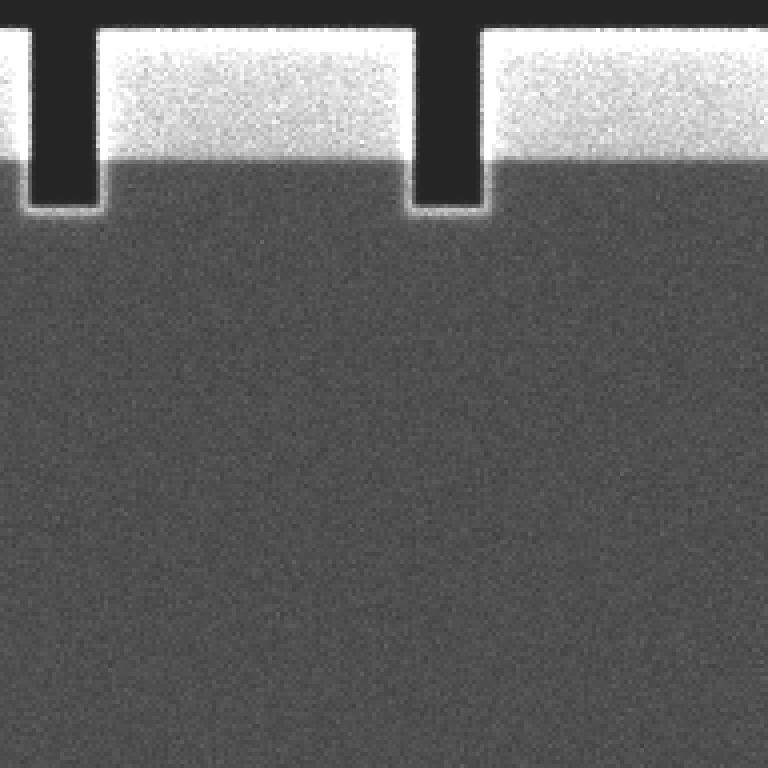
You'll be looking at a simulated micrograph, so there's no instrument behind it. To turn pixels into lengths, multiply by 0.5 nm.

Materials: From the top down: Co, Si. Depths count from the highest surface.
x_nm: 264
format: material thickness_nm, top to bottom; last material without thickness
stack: Co 64, Si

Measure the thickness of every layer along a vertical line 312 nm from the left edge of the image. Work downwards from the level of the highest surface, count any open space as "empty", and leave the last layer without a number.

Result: Co 64, Si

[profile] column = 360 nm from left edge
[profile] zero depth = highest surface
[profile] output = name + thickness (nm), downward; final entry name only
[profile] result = Co 64, Si